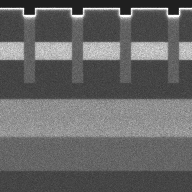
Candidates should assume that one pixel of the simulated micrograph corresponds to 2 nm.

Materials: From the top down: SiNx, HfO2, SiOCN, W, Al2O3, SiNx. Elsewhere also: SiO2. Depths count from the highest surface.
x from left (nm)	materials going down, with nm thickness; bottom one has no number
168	SiNx 68, HfO2 36, SiOCN 78, W 76, Al2O3 68, SiNx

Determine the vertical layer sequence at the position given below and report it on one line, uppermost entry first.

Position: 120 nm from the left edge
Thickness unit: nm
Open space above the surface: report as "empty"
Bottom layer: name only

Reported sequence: SiNx 68, HfO2 36, SiOCN 78, W 76, Al2O3 68, SiNx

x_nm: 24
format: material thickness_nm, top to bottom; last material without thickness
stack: SiNx 68, HfO2 36, SiOCN 78, W 76, Al2O3 68, SiNx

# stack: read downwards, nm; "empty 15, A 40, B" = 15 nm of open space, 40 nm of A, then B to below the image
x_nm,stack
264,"SiNx 68, HfO2 36, SiOCN 78, W 76, Al2O3 68, SiNx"